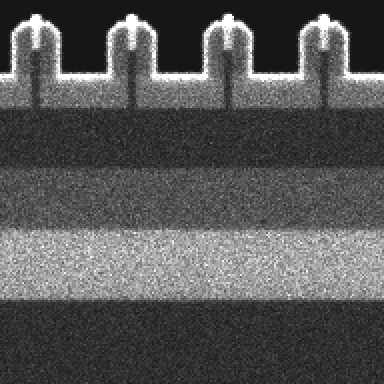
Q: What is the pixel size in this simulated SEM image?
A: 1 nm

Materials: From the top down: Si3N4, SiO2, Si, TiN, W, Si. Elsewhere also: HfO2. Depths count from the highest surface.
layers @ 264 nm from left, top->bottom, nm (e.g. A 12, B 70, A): empty 58, SiO2 34, Si 60, TiN 62, W 70, Si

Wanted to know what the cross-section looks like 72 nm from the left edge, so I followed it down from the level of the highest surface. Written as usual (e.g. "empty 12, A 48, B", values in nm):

empty 58, SiO2 34, Si 60, TiN 62, W 70, Si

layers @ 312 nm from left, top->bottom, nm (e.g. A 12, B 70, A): empty 6, Si3N4 52, SiO2 34, Si 60, TiN 62, W 70, Si